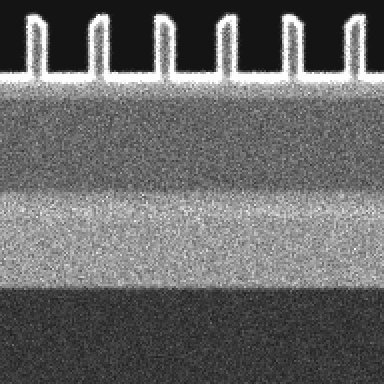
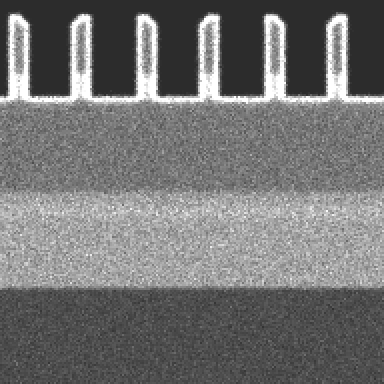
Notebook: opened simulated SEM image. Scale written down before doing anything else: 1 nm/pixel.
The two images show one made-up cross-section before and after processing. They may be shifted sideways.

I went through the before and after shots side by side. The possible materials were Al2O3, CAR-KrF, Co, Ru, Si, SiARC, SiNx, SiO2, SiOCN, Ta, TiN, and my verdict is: removed, SiO2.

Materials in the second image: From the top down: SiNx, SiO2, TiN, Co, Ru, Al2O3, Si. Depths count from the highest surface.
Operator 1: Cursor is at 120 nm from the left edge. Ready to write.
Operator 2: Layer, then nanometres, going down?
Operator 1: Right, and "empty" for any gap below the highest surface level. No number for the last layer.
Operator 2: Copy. empty 82, TiN 94, Co 14, Ru 12, Al2O3 70, Si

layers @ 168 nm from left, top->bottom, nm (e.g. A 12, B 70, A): empty 82, TiN 94, Co 14, Ru 12, Al2O3 70, Si